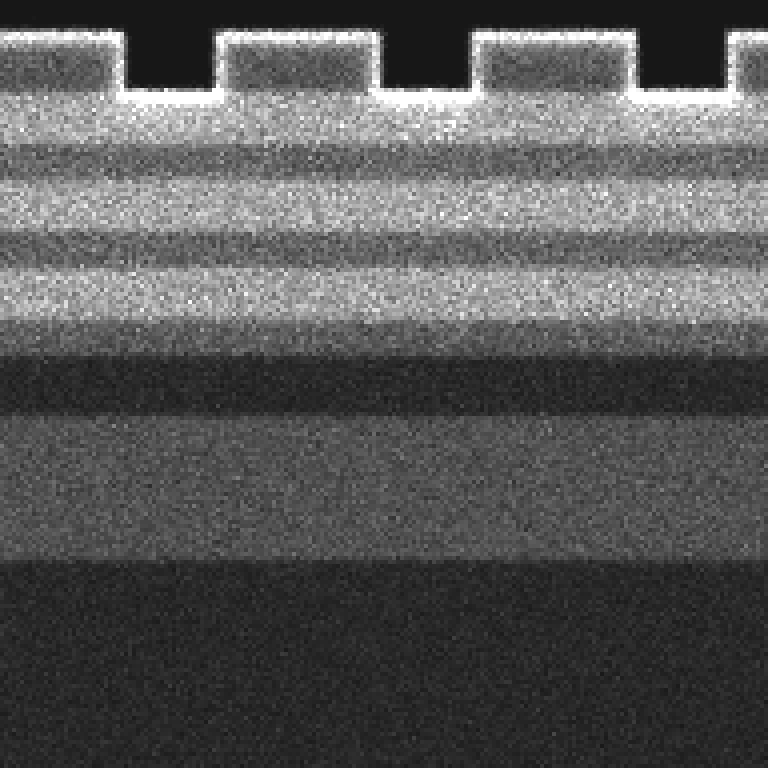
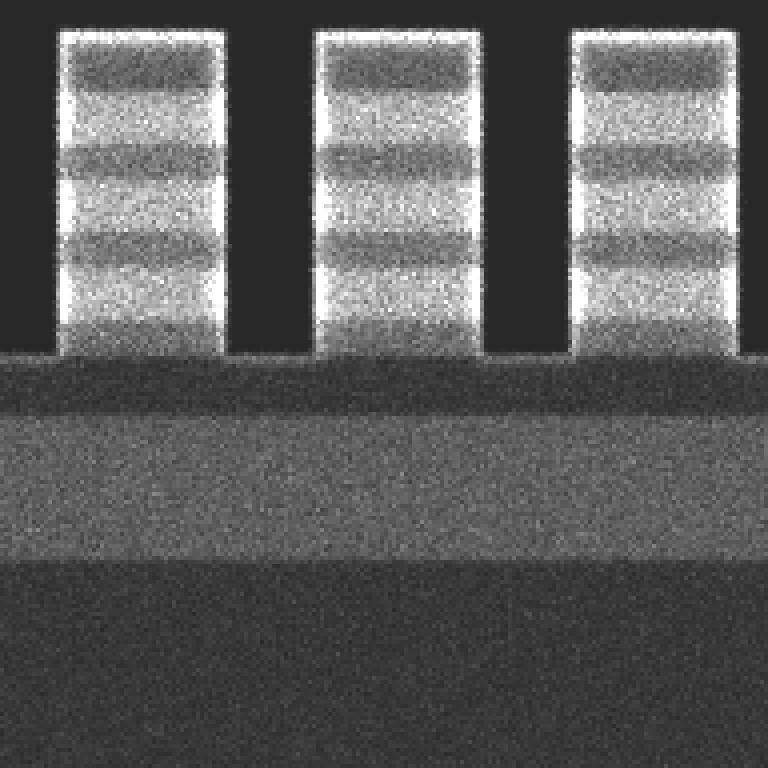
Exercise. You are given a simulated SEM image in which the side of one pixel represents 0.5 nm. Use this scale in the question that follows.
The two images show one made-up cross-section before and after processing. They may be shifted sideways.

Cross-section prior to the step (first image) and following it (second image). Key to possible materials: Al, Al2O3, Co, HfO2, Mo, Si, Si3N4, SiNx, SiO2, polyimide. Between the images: Co and HfO2 was removed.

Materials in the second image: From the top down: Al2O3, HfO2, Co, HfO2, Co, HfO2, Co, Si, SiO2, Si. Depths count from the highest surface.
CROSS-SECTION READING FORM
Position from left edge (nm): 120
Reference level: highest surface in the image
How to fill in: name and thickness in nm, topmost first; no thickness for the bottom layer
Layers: empty 162, Si 30, SiO2 72, Si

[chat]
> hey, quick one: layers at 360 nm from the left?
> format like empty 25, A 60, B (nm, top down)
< Al2O3 30, HfO2 26, Co 18, HfO2 26, Co 18, HfO2 26, Co 18, Si 30, SiO2 72, Si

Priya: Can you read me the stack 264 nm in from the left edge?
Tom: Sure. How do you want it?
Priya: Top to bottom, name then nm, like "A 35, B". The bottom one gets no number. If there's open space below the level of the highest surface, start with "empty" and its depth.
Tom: empty 162, Si 30, SiO2 72, Si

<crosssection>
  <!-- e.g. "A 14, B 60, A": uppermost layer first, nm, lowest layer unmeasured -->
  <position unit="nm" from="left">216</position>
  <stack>Al2O3 30, HfO2 26, Co 18, HfO2 26, Co 18, HfO2 26, Co 18, Si 30, SiO2 72, Si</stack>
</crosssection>